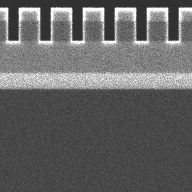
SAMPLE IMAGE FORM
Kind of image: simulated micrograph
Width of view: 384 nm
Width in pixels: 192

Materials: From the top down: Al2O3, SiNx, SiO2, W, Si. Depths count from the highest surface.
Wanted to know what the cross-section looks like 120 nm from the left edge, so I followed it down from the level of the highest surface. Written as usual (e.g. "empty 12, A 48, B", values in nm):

Al2O3 26, SiNx 40, SiO2 64, W 32, Si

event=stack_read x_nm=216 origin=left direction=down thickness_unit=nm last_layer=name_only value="empty 66, SiO2 64, W 32, Si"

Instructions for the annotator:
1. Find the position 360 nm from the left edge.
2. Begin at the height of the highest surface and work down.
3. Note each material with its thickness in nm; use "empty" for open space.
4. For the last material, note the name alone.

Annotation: Al2O3 26, SiNx 40, SiO2 64, W 32, Si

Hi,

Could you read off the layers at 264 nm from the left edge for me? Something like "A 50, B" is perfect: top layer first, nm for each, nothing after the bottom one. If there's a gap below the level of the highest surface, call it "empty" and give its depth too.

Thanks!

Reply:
Al2O3 26, SiNx 40, SiO2 64, W 32, Si